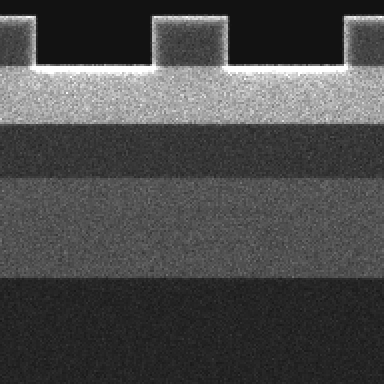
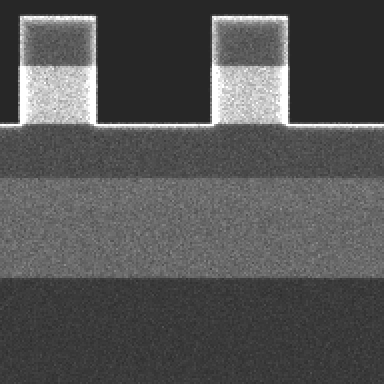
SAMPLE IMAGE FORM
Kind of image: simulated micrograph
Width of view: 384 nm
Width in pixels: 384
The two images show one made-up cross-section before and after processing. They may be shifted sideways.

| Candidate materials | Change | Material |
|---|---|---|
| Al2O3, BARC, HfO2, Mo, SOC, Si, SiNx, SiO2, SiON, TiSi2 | removed | HfO2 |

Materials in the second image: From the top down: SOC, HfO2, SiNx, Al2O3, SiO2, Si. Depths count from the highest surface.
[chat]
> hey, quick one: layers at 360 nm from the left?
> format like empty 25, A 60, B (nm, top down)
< empty 108, SiNx 54, Al2O3 30, SiO2 70, Si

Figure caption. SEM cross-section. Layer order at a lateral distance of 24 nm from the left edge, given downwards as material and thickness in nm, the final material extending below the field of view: SOC 50, HfO2 58, SiNx 54, Al2O3 30, SiO2 70, Si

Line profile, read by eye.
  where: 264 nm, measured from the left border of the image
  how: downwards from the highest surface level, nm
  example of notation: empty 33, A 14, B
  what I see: SOC 50, HfO2 58, SiNx 54, Al2O3 30, SiO2 70, Si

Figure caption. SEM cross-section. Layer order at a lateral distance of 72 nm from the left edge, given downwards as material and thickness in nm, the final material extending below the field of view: SOC 50, HfO2 58, SiNx 54, Al2O3 30, SiO2 70, Si